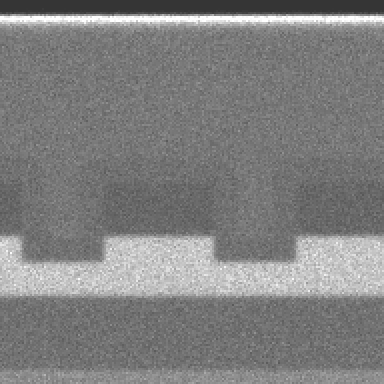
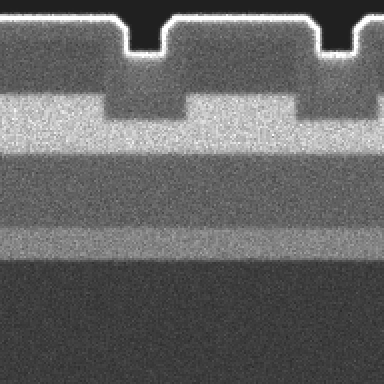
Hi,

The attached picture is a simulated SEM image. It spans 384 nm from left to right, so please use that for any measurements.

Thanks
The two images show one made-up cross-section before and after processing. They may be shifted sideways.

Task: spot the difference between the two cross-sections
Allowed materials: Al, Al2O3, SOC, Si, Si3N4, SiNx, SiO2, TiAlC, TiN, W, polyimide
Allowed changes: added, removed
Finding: removed SOC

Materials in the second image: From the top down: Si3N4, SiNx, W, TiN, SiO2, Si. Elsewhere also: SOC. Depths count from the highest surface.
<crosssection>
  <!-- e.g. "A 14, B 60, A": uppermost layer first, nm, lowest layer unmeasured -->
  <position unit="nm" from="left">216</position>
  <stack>Si3N4 24, SiNx 54, W 60, TiN 74, SiO2 32, Si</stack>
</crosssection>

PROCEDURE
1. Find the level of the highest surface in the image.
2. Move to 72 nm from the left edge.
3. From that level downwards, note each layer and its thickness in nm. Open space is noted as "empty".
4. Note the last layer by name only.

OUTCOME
Si3N4 24, SiNx 54, W 60, TiN 74, SiO2 32, Si